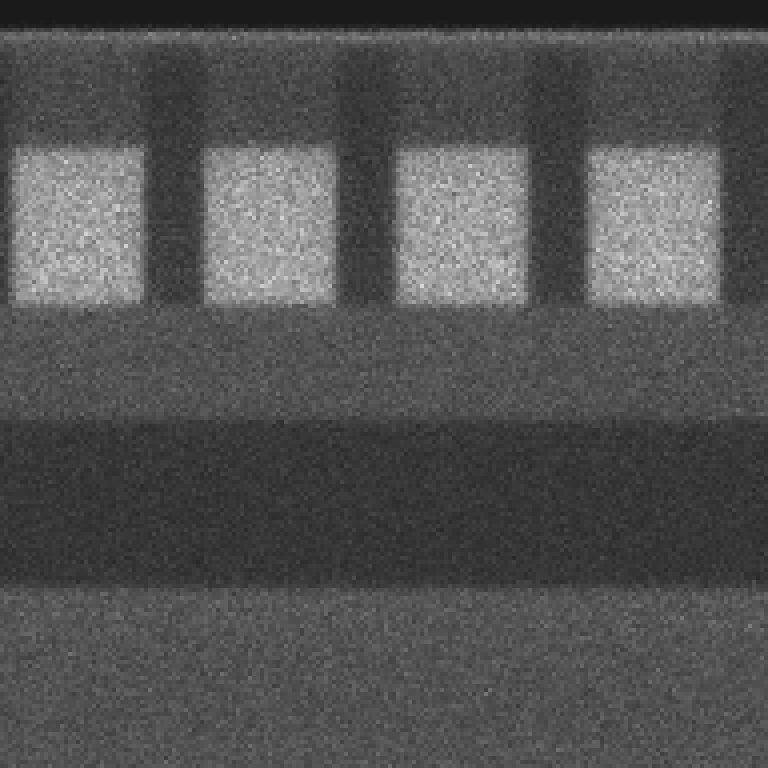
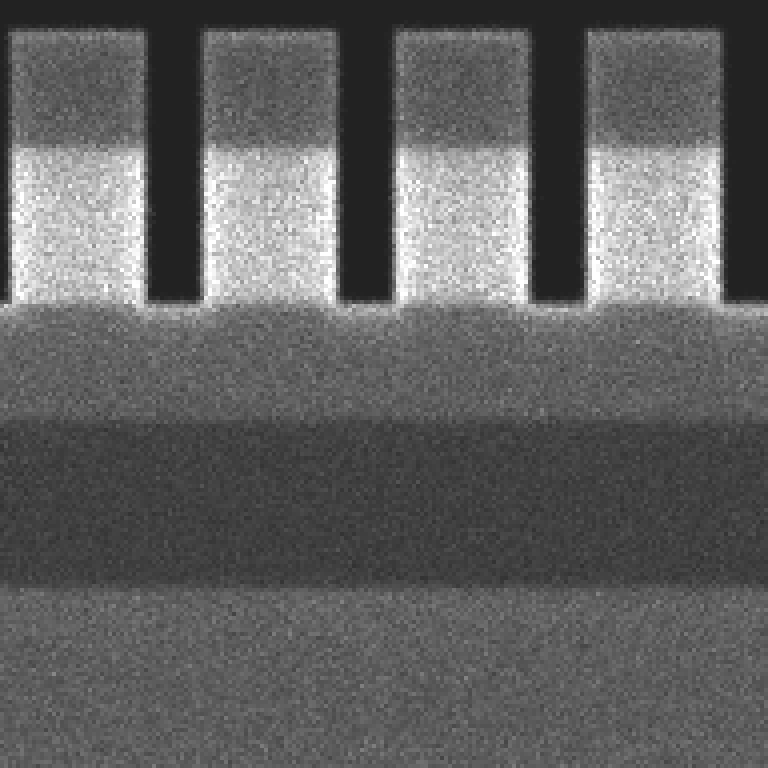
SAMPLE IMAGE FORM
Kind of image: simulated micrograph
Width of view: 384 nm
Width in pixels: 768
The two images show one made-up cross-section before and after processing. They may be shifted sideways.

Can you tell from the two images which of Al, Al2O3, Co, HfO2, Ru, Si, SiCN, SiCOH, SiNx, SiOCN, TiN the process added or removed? Yes, it removed SiNx.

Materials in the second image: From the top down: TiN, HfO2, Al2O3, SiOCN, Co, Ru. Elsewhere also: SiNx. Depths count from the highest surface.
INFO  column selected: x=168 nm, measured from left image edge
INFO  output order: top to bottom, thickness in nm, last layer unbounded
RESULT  empty 136, Al2O3 58, SiOCN 84, Co 74, Ru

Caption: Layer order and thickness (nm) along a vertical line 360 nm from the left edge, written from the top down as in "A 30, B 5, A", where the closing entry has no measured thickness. empty 136, Al2O3 58, SiOCN 84, Co 74, Ru